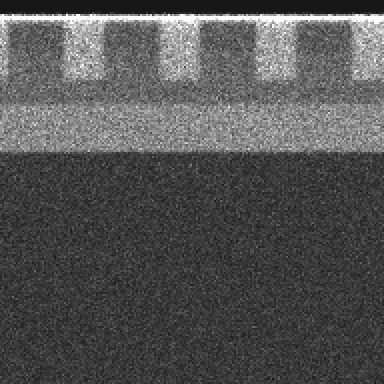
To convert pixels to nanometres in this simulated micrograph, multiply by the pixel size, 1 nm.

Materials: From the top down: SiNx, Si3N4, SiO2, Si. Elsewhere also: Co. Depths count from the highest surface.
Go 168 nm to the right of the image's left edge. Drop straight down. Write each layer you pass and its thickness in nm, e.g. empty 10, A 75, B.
Co 64, Si3N4 24, SiO2 48, Si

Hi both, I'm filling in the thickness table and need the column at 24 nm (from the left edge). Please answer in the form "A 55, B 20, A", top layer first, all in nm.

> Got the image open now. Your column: SiNx 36, Si3N4 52, SiO2 48, Si